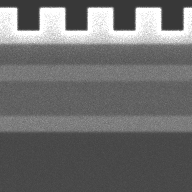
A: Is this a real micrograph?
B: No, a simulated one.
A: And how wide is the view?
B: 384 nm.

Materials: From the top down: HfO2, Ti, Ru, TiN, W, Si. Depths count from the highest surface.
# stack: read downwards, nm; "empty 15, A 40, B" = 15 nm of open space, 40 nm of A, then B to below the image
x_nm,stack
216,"HfO2 72, Ti 42, Ru 32, TiN 70, W 32, Si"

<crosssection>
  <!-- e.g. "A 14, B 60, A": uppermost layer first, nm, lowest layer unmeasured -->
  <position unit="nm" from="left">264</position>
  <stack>empty 46, HfO2 26, Ti 42, Ru 32, TiN 70, W 32, Si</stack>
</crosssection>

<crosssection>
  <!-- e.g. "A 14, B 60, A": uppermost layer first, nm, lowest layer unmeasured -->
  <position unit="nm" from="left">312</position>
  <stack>HfO2 72, Ti 42, Ru 32, TiN 70, W 32, Si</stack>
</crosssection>